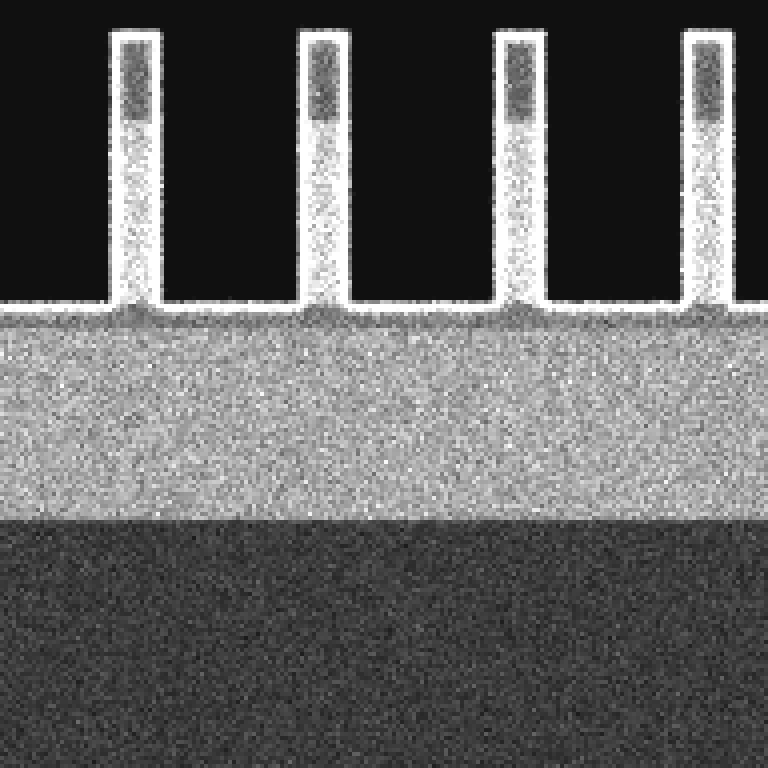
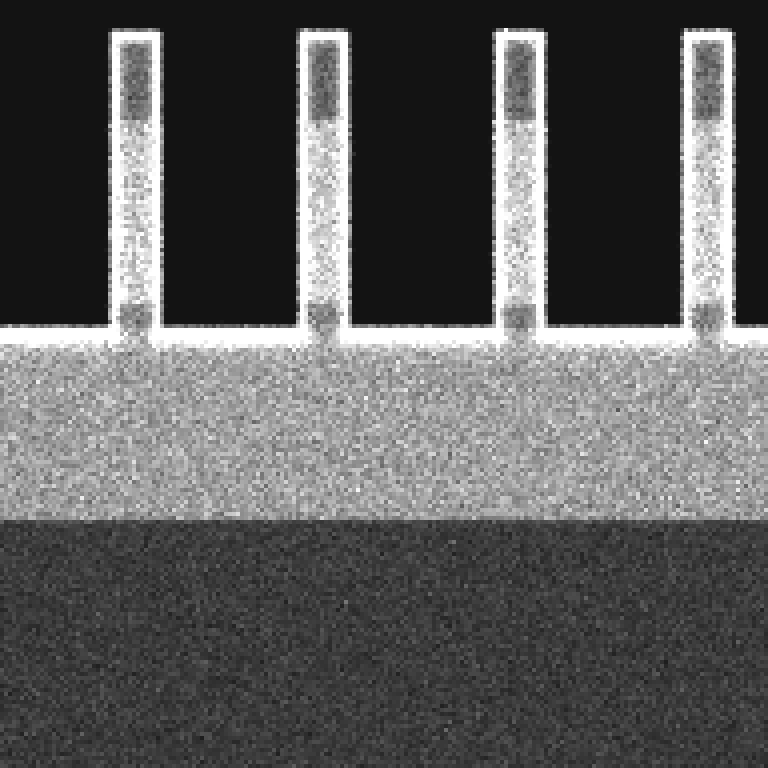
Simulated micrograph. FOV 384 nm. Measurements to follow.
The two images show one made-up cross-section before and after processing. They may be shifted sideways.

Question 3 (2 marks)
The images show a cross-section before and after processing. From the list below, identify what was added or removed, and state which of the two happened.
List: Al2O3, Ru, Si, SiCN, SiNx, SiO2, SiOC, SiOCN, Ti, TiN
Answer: TiN was removed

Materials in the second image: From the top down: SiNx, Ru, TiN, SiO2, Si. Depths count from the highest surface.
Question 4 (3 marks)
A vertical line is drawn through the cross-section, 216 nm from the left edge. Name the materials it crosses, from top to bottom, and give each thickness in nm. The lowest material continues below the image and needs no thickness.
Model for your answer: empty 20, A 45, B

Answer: empty 148, SiO2 96, Si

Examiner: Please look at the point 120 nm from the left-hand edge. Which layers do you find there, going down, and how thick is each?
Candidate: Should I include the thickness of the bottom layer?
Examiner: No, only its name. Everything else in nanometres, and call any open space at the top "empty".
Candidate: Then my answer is empty 148, SiO2 96, Si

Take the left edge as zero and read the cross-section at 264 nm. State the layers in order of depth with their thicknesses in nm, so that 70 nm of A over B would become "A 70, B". SiNx 44, Ru 92, TiN 12, SiO2 96, Si